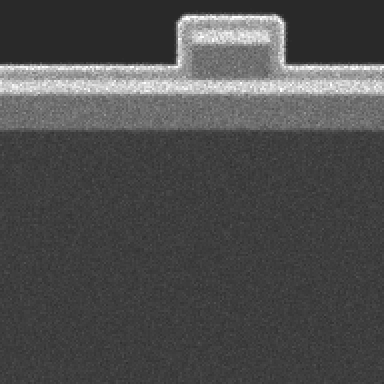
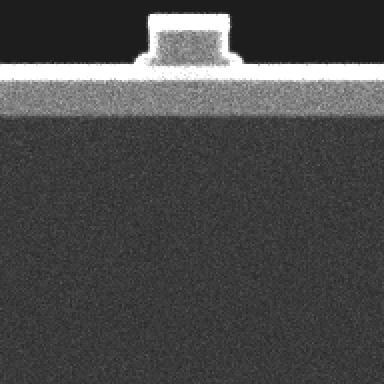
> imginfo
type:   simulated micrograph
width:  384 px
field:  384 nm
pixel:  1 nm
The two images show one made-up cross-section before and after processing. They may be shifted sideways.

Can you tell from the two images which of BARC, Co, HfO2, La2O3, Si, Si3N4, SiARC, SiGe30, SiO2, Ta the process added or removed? Yes, it removed Co.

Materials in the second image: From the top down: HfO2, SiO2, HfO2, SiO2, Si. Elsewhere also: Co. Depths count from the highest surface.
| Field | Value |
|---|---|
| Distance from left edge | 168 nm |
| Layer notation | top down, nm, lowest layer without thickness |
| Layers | HfO2 14, SiO2 36, HfO2 14, SiO2 36, Si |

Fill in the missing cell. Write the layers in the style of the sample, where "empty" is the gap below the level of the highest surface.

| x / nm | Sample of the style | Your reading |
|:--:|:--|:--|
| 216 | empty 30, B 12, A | HfO2 14, SiO2 36, HfO2 14, SiO2 36, Si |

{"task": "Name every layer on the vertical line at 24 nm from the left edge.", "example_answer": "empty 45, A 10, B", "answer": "empty 50, HfO2 14, SiO2 36, Si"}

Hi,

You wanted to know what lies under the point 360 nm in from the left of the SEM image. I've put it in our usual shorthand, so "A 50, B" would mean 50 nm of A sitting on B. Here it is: empty 50, HfO2 14, SiO2 36, Si